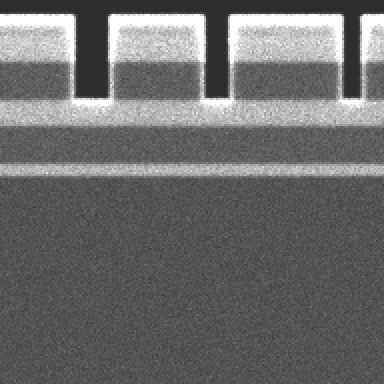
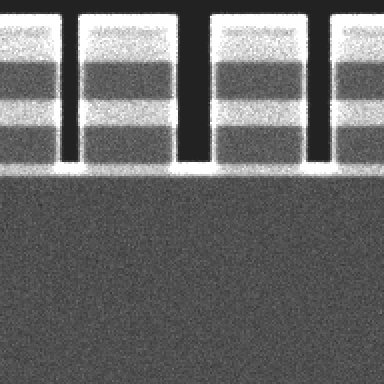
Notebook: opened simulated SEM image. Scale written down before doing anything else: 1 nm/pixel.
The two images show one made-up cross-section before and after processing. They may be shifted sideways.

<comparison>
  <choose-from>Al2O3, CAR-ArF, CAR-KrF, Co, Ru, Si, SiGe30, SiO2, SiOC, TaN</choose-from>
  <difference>Ru and SiGe30 removed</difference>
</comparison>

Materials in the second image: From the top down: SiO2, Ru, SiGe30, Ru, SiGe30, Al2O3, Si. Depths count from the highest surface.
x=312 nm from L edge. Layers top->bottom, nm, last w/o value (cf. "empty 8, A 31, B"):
empty 148, Al2O3 12, Si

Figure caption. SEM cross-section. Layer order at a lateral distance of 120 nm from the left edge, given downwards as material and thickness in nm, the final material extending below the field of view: SiO2 20, Ru 26, SiGe30 38, Ru 26, SiGe30 38, Al2O3 12, Si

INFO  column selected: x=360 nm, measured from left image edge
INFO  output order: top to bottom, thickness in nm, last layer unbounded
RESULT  SiO2 20, Ru 26, SiGe30 38, Ru 26, SiGe30 38, Al2O3 12, Si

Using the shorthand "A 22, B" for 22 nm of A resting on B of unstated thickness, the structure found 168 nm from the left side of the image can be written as SiO2 20, Ru 26, SiGe30 38, Ru 26, SiGe30 38, Al2O3 12, Si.